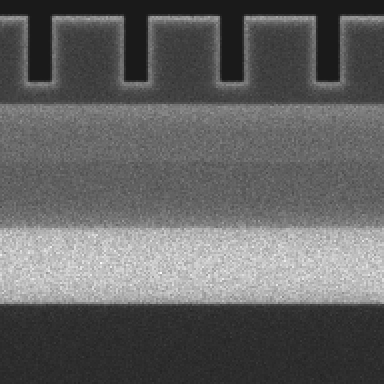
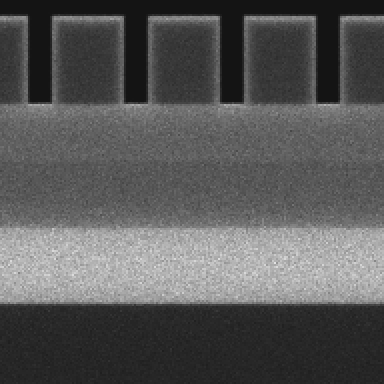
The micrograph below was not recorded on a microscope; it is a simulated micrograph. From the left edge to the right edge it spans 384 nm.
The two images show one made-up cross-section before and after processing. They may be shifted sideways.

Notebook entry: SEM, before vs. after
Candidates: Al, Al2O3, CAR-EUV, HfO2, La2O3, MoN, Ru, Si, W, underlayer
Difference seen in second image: underlayer removed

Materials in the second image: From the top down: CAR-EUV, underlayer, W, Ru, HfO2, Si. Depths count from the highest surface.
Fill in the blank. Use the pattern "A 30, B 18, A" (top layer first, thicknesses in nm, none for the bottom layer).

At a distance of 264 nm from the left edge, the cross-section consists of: CAR-EUV 66, underlayer 22, W 58, Ru 66, HfO2 76, Si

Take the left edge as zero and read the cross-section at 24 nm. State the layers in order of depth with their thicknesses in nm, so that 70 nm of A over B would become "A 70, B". CAR-EUV 66, underlayer 22, W 58, Ru 66, HfO2 76, Si